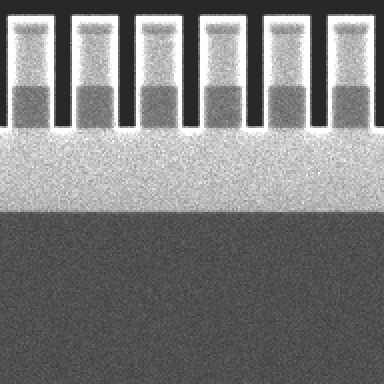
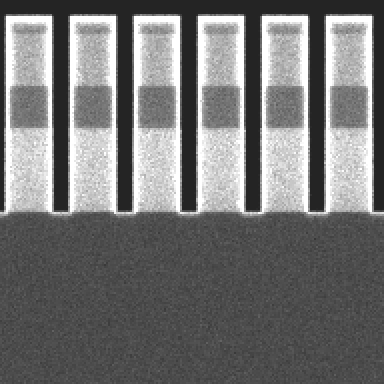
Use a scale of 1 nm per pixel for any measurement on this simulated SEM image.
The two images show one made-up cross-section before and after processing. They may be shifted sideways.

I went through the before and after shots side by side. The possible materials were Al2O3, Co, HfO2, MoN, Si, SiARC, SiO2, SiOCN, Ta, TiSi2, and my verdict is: removed, Co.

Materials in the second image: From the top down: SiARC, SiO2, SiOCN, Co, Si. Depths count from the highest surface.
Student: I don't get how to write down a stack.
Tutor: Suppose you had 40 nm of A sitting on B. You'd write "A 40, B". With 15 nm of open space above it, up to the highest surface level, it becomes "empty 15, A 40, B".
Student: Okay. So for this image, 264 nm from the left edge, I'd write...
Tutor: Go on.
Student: SiARC 18, SiO2 52, SiOCN 42, Co 84, Si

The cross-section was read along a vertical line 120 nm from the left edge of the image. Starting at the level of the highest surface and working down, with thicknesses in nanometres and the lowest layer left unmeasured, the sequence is empty 196, Si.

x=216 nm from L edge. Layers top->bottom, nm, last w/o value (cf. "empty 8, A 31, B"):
SiARC 18, SiO2 52, SiOCN 42, Co 84, Si